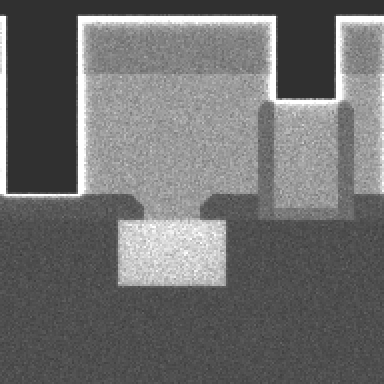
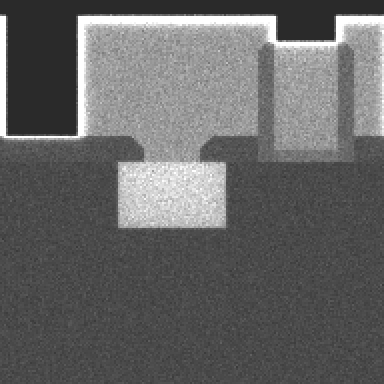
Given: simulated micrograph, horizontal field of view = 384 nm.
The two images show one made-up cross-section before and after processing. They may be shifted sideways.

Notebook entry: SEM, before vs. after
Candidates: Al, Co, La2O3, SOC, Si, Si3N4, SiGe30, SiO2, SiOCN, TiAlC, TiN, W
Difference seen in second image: SOC removed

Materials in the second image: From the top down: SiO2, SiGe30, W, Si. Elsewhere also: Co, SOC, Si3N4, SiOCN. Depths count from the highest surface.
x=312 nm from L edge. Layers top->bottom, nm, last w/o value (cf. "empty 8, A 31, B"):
empty 26, Co 108, Si3N4 12, Si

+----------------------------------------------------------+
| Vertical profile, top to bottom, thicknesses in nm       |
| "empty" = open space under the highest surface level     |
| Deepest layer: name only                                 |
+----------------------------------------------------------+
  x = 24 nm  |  empty 120, SiGe30 26, Si